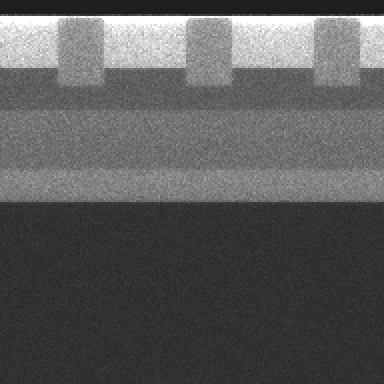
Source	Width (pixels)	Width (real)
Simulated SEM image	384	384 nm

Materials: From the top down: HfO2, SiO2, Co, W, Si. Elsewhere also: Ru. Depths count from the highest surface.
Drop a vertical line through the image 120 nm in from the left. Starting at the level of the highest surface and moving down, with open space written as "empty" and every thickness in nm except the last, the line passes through HfO2 52, SiO2 42, Co 60, W 32, Si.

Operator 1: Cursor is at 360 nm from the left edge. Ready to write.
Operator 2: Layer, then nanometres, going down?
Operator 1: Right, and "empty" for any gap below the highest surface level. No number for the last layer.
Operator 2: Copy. HfO2 52, SiO2 42, Co 60, W 32, Si